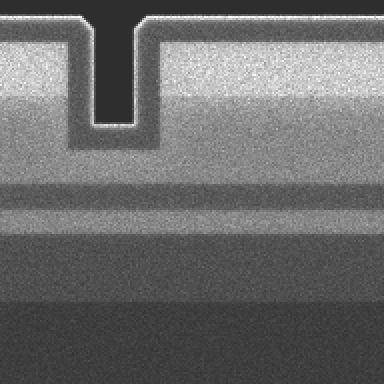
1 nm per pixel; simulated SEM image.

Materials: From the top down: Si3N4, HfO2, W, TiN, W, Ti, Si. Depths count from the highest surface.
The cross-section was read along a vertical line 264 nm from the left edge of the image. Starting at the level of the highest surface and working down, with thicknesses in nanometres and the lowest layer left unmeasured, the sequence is Si3N4 26, HfO2 54, W 88, TiN 26, W 24, Ti 68, Si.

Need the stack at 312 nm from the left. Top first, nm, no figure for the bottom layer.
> Si3N4 26, HfO2 54, W 88, TiN 26, W 24, Ti 68, Si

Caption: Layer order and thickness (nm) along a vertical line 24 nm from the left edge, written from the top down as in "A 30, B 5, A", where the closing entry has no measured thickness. Si3N4 26, HfO2 54, W 88, TiN 26, W 24, Ti 68, Si